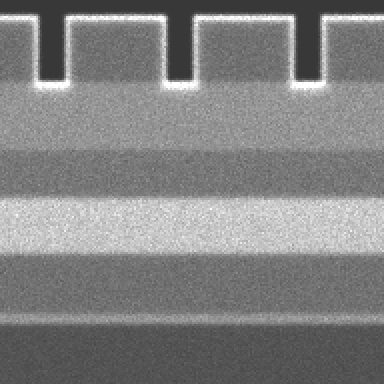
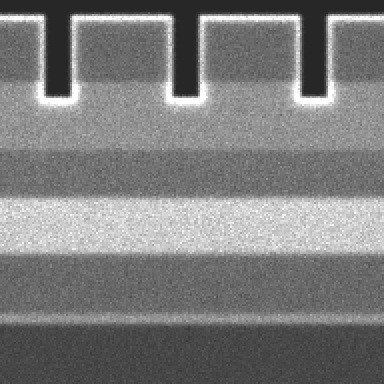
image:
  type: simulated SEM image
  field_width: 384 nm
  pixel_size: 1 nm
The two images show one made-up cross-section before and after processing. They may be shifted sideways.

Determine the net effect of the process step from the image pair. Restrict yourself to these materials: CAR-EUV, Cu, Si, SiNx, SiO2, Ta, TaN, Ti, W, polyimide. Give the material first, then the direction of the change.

SiO2: removed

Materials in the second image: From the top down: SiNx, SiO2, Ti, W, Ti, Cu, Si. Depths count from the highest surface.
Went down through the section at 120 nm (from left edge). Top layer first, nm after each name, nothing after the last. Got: SiNx 66, SiO2 68, Ti 48, W 56, Ti 60, Cu 10, Si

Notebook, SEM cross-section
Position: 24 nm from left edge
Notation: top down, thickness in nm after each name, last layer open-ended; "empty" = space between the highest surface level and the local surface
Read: SiNx 66, SiO2 68, Ti 48, W 56, Ti 60, Cu 10, Si